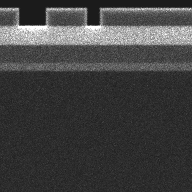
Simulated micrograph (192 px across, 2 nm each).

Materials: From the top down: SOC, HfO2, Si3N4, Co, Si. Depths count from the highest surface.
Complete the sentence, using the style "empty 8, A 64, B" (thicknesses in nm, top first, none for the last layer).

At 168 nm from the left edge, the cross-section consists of SOC 36, HfO2 38, Si3N4 36, Co 16, Si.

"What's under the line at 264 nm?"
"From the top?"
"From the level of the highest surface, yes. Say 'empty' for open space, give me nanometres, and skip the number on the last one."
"SOC 36, HfO2 38, Si3N4 36, Co 16, Si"